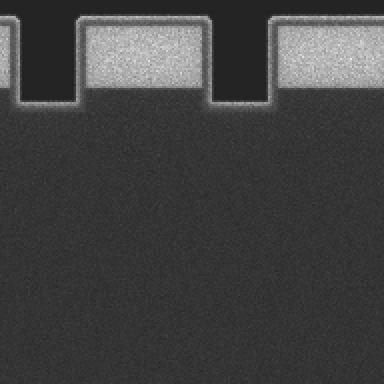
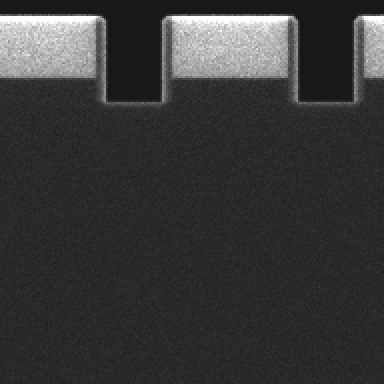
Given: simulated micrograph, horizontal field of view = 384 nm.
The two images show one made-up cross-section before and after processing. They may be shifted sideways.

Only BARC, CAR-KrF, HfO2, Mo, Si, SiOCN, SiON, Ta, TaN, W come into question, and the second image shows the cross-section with SiOCN removed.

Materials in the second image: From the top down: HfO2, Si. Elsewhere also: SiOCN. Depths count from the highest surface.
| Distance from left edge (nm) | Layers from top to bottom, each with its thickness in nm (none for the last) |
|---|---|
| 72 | HfO2 62, Si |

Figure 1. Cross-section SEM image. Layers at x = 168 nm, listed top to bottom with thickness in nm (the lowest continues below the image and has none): SiOCN 86, Si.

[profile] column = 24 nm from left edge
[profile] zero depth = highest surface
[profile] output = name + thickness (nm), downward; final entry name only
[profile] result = HfO2 62, Si